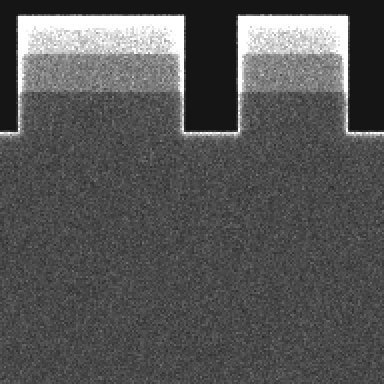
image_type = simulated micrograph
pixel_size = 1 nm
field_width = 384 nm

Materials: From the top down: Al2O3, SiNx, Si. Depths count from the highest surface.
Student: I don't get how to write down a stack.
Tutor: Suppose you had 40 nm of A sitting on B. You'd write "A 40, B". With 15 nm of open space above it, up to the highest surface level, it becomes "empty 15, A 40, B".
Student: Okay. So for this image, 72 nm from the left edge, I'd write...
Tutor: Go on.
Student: Al2O3 38, SiNx 38, Si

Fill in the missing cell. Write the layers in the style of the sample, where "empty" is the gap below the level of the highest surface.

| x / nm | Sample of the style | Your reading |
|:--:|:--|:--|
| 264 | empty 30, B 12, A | Al2O3 38, SiNx 38, Si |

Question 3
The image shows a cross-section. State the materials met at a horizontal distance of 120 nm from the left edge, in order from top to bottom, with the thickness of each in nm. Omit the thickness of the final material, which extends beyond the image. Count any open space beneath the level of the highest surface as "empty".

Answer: Al2O3 38, SiNx 38, Si